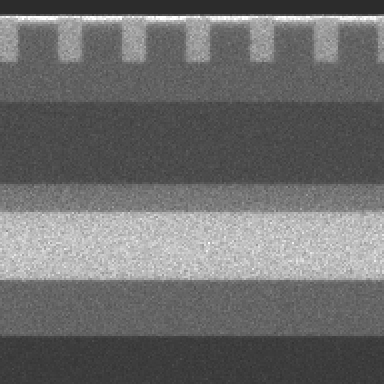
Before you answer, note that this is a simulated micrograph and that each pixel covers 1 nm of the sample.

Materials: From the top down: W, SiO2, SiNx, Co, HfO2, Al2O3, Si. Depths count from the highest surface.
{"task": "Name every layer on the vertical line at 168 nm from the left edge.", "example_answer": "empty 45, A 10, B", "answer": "SiO2 86, SiNx 82, Co 28, HfO2 68, Al2O3 56, Si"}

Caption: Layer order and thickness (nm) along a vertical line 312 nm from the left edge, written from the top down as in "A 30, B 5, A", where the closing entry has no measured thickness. SiO2 86, SiNx 82, Co 28, HfO2 68, Al2O3 56, Si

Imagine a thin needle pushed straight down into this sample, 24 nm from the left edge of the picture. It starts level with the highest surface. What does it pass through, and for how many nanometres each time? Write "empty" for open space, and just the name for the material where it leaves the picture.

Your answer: SiO2 86, SiNx 82, Co 28, HfO2 68, Al2O3 56, Si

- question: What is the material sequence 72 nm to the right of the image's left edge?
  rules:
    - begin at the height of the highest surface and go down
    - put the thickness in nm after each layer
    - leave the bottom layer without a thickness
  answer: W 46, SiO2 40, SiNx 82, Co 28, HfO2 68, Al2O3 56, Si